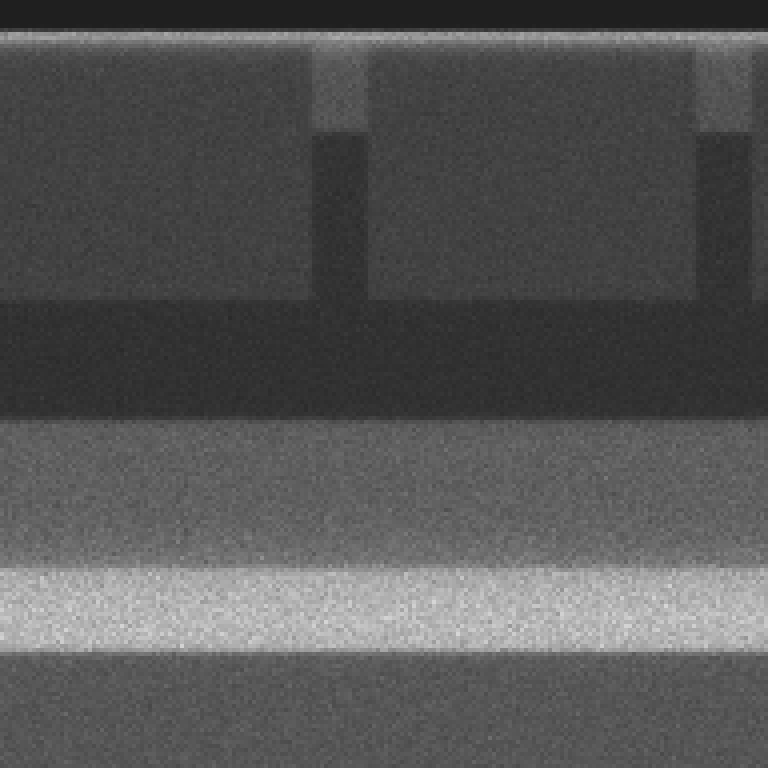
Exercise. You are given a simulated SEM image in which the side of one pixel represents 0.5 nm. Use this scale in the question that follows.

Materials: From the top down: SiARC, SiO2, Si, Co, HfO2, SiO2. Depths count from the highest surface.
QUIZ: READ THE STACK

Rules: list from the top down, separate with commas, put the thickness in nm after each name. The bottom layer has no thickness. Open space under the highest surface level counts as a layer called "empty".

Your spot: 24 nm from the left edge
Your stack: SiARC 134, Si 60, Co 74, HfO2 42, SiO2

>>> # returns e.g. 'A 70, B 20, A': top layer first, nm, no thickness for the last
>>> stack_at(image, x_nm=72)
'SiARC 134, Si 60, Co 74, HfO2 42, SiO2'